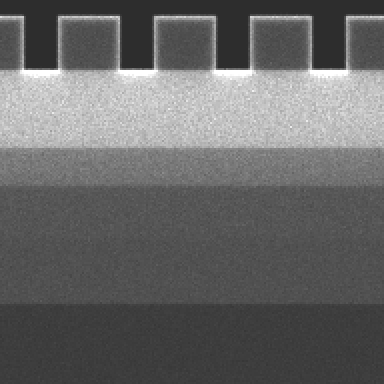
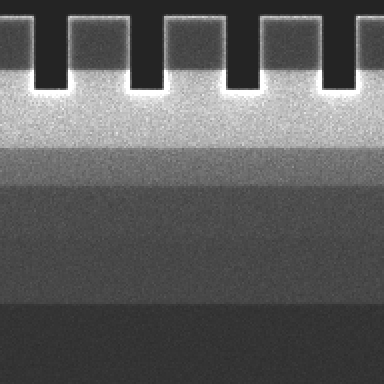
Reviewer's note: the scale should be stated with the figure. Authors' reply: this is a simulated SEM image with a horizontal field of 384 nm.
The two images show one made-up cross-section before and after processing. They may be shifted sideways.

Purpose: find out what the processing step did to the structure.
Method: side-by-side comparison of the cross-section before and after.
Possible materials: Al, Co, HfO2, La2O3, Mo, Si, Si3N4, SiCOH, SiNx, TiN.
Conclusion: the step removed HfO2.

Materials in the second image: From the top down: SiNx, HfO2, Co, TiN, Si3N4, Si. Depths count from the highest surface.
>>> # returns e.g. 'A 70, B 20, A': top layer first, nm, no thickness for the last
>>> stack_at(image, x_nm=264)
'SiNx 54, HfO2 78, Co 38, TiN 52, Si3N4 66, Si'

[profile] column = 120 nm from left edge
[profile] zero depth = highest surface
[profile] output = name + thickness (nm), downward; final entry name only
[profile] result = SiNx 54, HfO2 78, Co 38, TiN 52, Si3N4 66, Si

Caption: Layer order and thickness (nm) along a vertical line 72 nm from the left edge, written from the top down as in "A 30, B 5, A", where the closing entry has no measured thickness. SiNx 54, HfO2 78, Co 38, TiN 52, Si3N4 66, Si